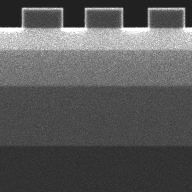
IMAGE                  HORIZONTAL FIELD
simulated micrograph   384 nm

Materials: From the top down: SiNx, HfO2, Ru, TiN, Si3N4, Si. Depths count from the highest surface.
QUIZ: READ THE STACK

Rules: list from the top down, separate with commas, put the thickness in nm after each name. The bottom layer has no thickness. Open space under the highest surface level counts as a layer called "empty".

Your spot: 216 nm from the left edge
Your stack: SiNx 40, HfO2 44, Ru 72, TiN 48, Si3N4 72, Si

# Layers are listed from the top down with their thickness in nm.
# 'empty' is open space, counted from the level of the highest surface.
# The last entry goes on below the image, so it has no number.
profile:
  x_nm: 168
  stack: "empty 40, HfO2 44, Ru 72, TiN 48, Si3N4 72, Si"